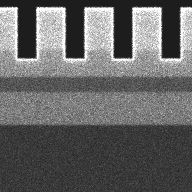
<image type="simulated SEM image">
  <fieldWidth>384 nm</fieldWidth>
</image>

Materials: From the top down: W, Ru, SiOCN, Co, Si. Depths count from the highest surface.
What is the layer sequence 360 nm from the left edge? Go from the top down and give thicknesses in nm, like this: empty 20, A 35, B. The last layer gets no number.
empty 102, Ru 36, SiOCN 30, Co 66, Si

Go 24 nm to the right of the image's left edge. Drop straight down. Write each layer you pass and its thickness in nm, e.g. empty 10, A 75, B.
W 84, Ru 54, SiOCN 30, Co 66, Si